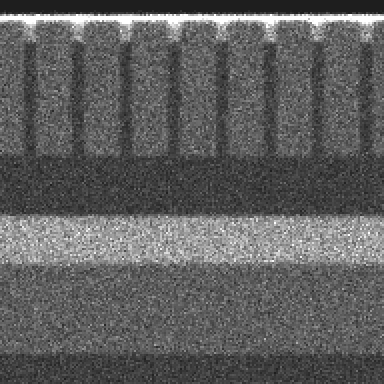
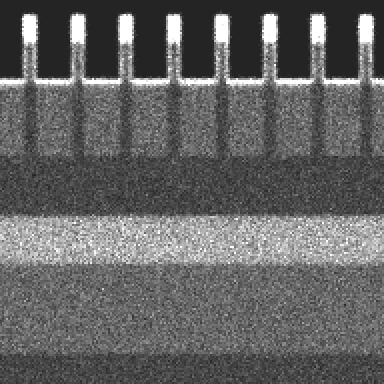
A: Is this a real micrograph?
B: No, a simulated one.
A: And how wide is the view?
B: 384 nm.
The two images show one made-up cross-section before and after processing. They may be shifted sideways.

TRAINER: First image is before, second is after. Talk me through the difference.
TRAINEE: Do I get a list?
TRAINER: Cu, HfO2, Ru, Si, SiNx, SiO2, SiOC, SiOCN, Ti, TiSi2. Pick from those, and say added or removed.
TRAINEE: removed: SiNx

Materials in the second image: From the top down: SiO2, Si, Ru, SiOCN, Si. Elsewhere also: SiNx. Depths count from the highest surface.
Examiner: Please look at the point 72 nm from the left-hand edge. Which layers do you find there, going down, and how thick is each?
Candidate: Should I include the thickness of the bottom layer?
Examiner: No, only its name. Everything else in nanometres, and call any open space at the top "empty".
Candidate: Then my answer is SiO2 26, Si 174, Ru 48, SiOCN 90, Si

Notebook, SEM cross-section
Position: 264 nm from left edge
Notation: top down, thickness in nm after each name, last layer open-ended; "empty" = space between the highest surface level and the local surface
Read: SiO2 26, Si 174, Ru 48, SiOCN 90, Si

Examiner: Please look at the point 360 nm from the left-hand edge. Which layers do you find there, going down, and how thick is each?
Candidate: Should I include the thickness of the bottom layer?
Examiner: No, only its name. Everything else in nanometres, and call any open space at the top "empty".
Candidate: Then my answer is SiO2 26, Si 174, Ru 48, SiOCN 90, Si